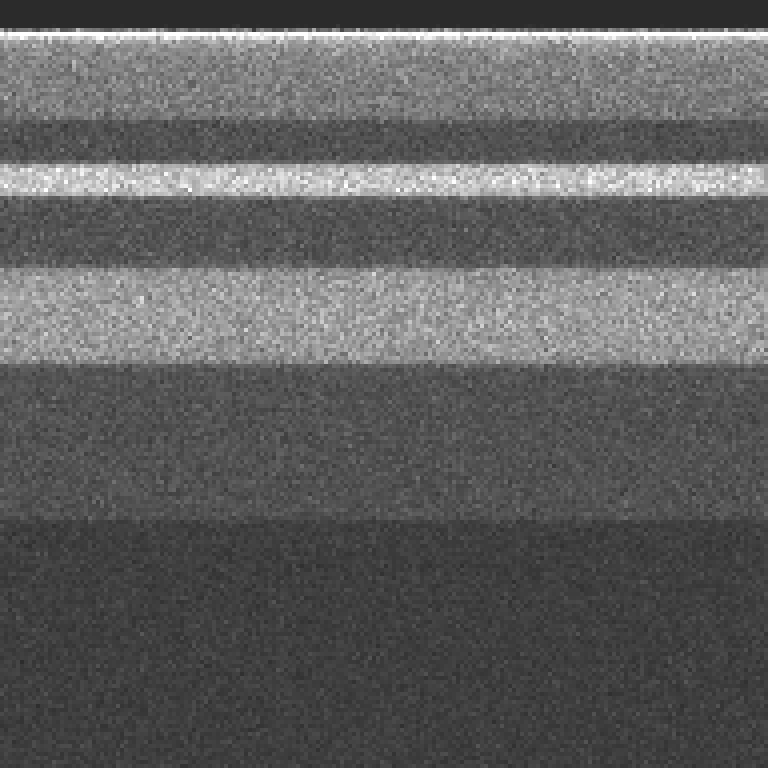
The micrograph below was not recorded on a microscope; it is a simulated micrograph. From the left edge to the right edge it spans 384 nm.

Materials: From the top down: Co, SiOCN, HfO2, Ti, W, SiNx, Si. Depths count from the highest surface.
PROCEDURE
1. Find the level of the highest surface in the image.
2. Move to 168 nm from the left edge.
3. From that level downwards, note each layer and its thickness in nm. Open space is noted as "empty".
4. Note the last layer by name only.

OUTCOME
Co 44, SiOCN 22, HfO2 16, Ti 36, W 48, SiNx 78, Si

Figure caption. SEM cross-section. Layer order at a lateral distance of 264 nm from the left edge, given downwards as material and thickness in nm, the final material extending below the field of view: Co 44, SiOCN 22, HfO2 16, Ti 36, W 48, SiNx 78, Si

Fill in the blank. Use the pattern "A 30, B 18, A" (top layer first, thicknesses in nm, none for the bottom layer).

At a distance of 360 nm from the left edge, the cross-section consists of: Co 44, SiOCN 22, HfO2 16, Ti 36, W 48, SiNx 78, Si